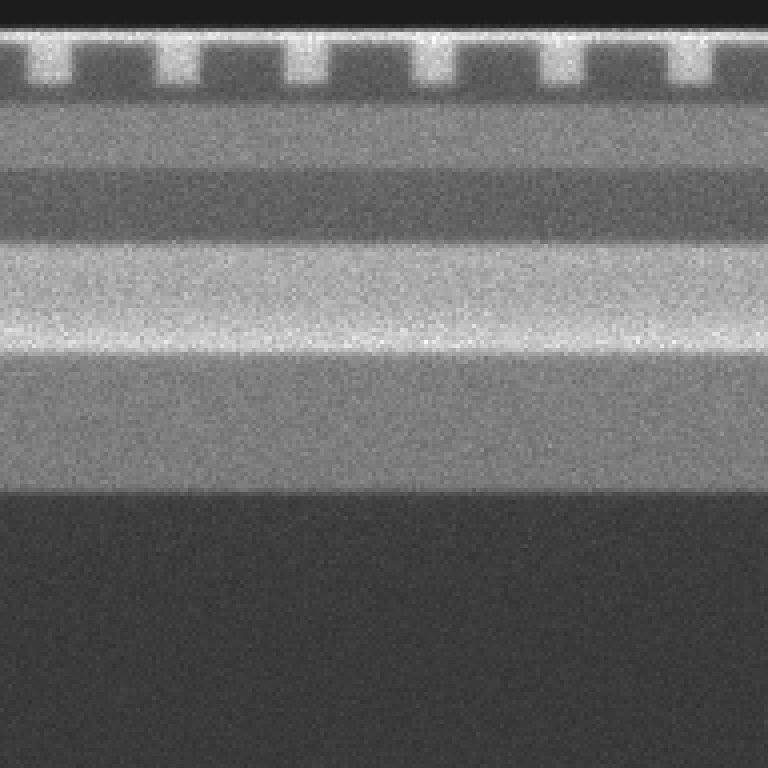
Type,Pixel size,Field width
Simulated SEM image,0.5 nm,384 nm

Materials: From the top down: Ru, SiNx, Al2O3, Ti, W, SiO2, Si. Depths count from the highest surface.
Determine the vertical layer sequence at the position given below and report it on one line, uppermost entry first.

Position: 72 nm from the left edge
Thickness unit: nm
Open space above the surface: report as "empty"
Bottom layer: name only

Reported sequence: SiNx 36, Al2O3 32, Ti 38, W 54, SiO2 70, Si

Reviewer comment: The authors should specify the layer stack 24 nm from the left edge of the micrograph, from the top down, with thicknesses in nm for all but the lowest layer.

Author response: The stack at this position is Ru 26, SiNx 10, Al2O3 32, Ti 38, W 54, SiO2 70, Si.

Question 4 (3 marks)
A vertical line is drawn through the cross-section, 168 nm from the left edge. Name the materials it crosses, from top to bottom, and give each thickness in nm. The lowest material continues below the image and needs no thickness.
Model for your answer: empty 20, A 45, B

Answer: SiNx 36, Al2O3 32, Ti 38, W 54, SiO2 70, Si